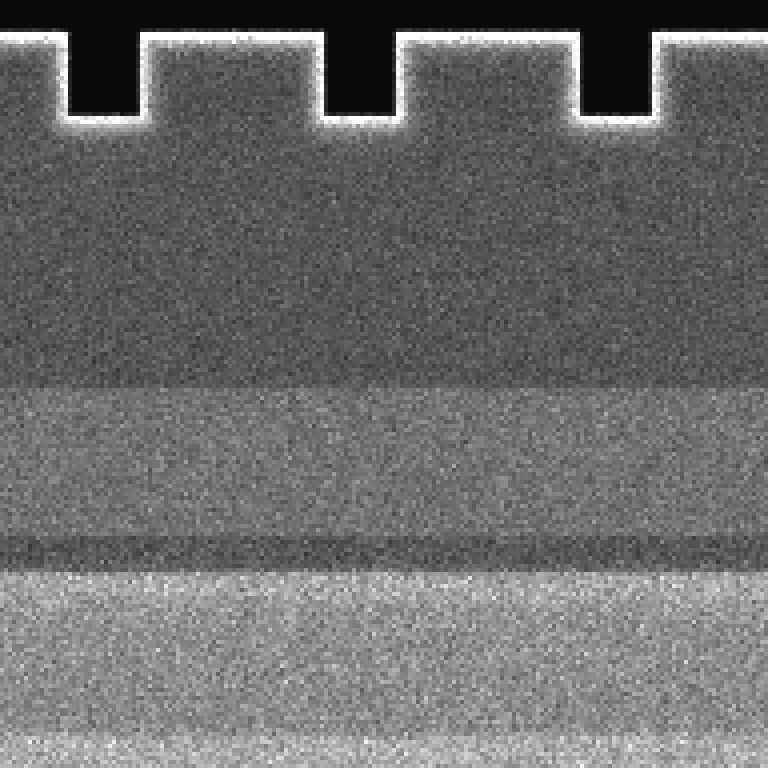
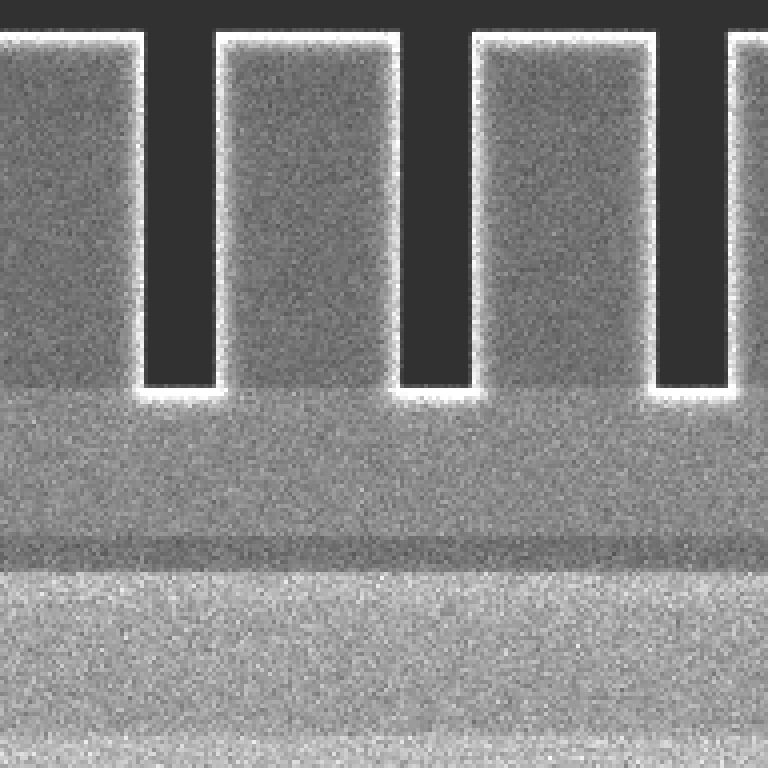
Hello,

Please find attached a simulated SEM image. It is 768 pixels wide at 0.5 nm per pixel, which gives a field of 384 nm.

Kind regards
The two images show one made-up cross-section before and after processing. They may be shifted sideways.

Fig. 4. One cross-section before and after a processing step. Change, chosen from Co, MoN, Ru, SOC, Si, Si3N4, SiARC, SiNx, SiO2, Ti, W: SOC removed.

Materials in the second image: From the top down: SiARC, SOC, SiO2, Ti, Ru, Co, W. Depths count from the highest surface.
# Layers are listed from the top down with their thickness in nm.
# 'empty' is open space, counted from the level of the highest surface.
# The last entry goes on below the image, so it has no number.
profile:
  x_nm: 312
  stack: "SiARC 42, SOC 136, SiO2 74, Ti 18, Ru 14, Co 68, W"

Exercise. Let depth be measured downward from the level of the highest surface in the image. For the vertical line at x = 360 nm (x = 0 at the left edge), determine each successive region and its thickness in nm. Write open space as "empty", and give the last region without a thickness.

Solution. empty 178, SiO2 74, Ti 18, Ru 14, Co 68, W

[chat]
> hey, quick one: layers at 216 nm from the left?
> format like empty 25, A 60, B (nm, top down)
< empty 178, SiO2 74, Ti 18, Ru 14, Co 68, W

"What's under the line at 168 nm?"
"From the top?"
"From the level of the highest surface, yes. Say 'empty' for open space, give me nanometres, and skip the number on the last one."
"SiARC 42, SOC 136, SiO2 74, Ti 18, Ru 14, Co 68, W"